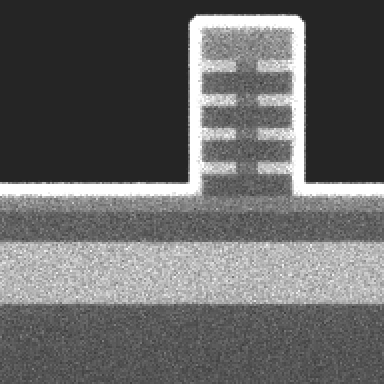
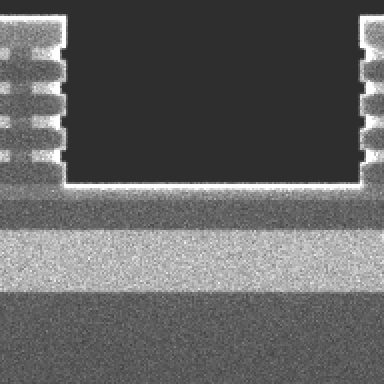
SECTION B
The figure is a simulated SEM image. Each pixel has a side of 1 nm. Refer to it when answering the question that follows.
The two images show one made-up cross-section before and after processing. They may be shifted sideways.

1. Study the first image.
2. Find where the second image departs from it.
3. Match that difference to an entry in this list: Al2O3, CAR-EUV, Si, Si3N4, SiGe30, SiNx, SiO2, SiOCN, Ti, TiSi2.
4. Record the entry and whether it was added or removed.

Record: Al2O3 / removed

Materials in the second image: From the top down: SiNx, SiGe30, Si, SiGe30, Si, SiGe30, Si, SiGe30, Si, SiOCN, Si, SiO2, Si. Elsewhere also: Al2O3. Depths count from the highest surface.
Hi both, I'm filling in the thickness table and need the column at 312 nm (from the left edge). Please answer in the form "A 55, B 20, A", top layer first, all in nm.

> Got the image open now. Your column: empty 168, SiOCN 16, Si 30, SiO2 62, Si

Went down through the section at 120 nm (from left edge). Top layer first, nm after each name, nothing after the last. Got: empty 168, SiOCN 16, Si 30, SiO2 62, Si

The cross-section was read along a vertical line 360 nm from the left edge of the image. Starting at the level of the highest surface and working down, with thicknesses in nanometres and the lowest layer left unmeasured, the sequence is SiNx 32, empty 12, Si 22, empty 12, Si 22, empty 12, Si 22, empty 12, Si 22, SiOCN 16, Si 30, SiO2 62, Si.